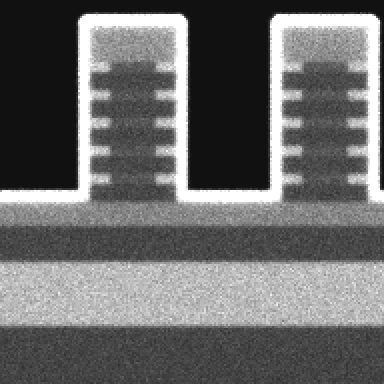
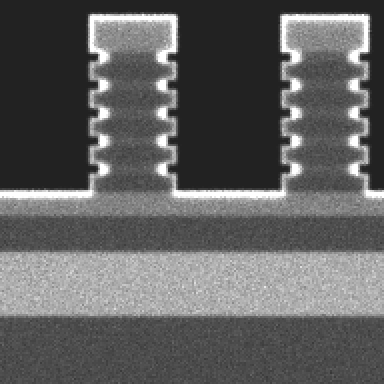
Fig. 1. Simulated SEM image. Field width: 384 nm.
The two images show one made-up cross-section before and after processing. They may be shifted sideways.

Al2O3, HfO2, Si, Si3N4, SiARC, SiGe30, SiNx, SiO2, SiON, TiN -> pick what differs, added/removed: Al2O3 removed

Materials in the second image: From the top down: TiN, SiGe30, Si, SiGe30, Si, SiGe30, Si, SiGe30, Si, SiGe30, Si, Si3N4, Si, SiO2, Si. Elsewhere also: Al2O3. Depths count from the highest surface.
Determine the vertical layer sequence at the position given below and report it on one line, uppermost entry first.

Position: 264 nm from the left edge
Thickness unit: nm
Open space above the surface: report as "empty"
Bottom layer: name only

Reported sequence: empty 176, Si3N4 24, Si 36, SiO2 64, Si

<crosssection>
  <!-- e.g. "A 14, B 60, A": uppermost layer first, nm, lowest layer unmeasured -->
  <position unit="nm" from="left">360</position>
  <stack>TiN 36, empty 10, Si 18, empty 10, Si 18, empty 10, Si 18, empty 10, Si 18, empty 10, Si 18, Si3N4 24, Si 36, SiO2 64, Si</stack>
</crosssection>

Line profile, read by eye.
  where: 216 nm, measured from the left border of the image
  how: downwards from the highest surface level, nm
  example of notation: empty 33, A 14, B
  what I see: empty 176, Si3N4 24, Si 36, SiO2 64, Si